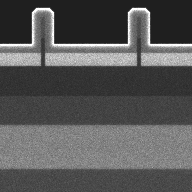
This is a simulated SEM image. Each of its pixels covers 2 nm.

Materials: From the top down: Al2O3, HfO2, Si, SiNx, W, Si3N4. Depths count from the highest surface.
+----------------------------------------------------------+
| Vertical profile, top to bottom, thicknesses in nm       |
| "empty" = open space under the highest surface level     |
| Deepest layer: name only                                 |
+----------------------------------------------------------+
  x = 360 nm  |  empty 72, Al2O3 18, HfO2 26, Si 60, SiNx 58, W 88, Si3N4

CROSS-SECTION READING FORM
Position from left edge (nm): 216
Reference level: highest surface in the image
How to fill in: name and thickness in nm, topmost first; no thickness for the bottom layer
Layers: empty 72, Al2O3 18, HfO2 26, Si 60, SiNx 58, W 88, Si3N4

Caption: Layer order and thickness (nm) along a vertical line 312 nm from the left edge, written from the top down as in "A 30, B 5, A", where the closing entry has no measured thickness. empty 72, Al2O3 18, HfO2 26, Si 60, SiNx 58, W 88, Si3N4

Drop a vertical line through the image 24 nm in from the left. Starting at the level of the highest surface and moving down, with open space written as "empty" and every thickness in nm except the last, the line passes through empty 72, Al2O3 18, HfO2 26, Si 60, SiNx 58, W 88, Si3N4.